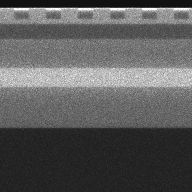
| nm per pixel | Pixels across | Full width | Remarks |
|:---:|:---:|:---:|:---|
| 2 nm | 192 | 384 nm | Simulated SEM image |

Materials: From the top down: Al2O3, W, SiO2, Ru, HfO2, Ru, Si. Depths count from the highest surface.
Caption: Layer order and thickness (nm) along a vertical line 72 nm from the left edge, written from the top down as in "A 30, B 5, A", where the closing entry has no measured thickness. W 32, SiO2 30, Ru 58, HfO2 38, Ru 82, Si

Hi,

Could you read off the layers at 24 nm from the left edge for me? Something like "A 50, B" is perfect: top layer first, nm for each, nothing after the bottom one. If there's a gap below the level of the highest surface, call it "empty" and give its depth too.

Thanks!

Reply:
W 32, SiO2 30, Ru 58, HfO2 38, Ru 82, Si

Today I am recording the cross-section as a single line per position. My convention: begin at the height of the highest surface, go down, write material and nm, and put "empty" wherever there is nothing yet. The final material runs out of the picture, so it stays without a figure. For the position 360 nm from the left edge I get Al2O3 22, W 10, SiO2 30, Ru 58, HfO2 38, Ru 82, Si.